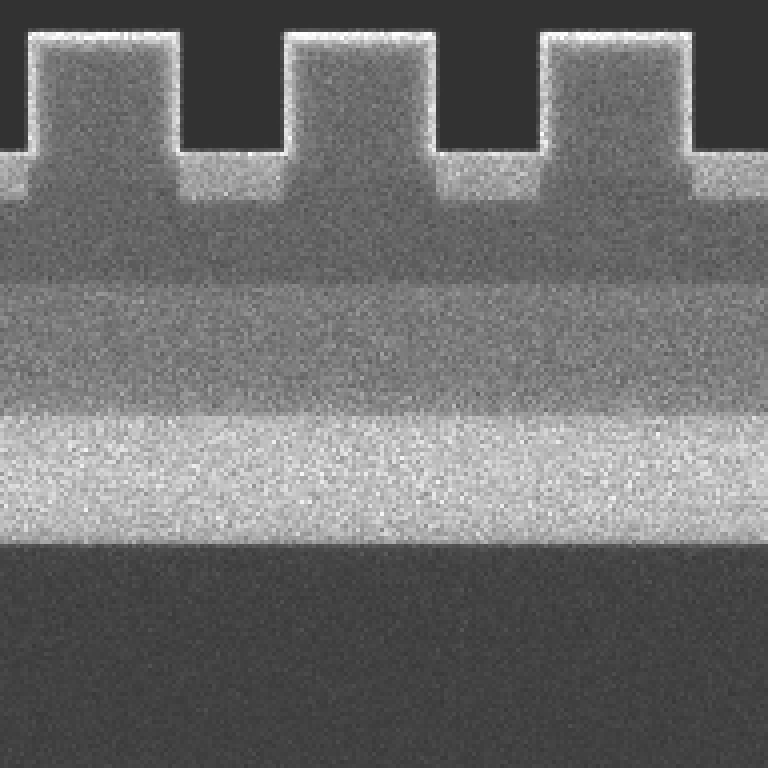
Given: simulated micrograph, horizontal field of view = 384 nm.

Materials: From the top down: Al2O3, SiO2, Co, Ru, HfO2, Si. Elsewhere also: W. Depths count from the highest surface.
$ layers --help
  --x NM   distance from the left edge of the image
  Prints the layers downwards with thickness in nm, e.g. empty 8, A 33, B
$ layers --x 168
Al2O3 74, SiO2 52, Co 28, Ru 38, HfO2 64, Si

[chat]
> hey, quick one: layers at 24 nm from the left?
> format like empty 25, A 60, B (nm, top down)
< Al2O3 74, SiO2 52, Co 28, Ru 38, HfO2 64, Si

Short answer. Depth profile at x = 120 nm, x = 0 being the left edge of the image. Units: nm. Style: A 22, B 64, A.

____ empty 60, W 24, SiO2 42, Co 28, Ru 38, HfO2 64, Si